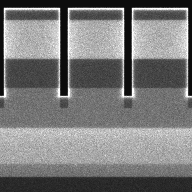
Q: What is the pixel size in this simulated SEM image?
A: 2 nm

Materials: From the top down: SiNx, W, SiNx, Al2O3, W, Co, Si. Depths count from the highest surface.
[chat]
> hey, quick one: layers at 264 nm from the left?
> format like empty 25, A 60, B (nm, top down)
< SiNx 24, W 78, SiNx 58, Al2O3 80, W 72, Co 26, Si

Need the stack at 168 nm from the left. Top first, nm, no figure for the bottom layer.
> SiNx 24, W 78, SiNx 58, Al2O3 80, W 72, Co 26, Si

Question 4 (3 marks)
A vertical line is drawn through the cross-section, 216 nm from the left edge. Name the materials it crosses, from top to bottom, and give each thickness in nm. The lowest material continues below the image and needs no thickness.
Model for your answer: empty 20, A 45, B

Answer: SiNx 24, W 78, SiNx 58, Al2O3 80, W 72, Co 26, Si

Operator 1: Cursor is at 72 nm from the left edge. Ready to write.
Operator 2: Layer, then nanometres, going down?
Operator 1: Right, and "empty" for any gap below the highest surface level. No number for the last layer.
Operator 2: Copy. SiNx 24, W 78, SiNx 58, Al2O3 80, W 72, Co 26, Si